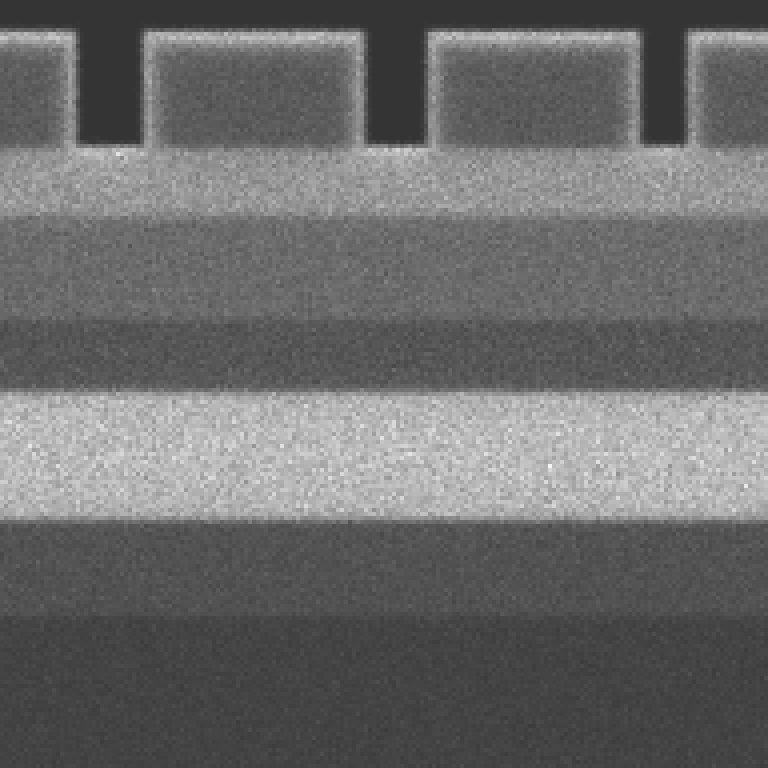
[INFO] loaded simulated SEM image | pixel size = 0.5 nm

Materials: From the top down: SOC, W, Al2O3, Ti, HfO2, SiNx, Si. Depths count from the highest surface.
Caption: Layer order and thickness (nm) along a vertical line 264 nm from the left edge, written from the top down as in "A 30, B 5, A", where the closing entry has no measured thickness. SOC 58, W 34, Al2O3 52, Ti 36, HfO2 64, SiNx 48, Si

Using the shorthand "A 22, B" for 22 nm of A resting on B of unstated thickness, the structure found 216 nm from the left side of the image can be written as SOC 58, W 34, Al2O3 52, Ti 36, HfO2 64, SiNx 48, Si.